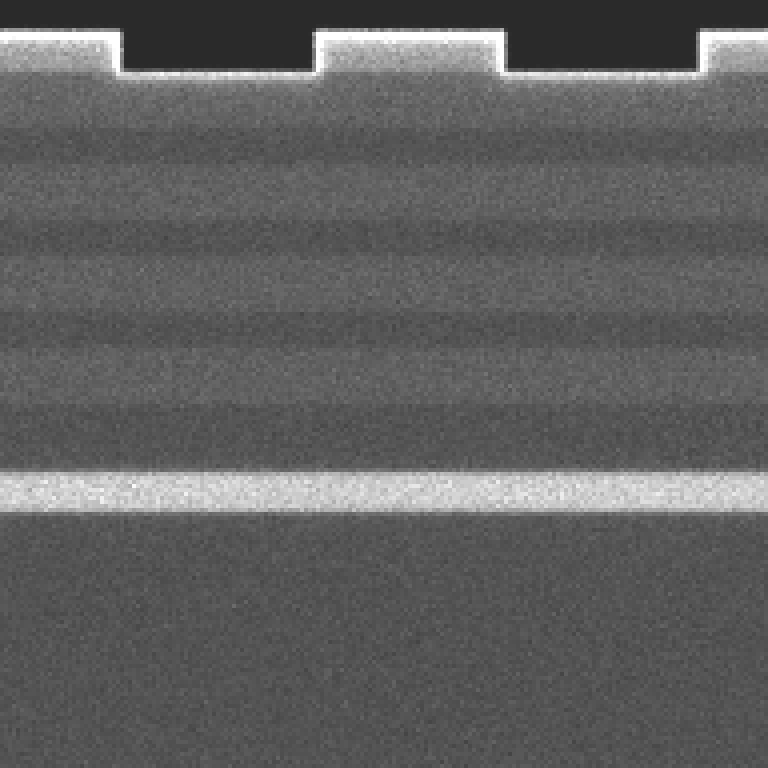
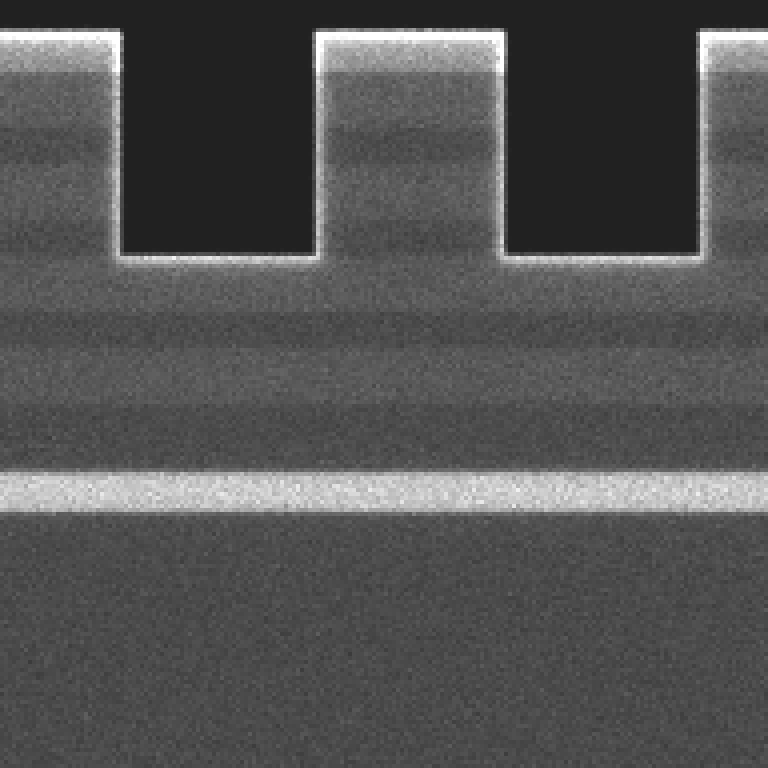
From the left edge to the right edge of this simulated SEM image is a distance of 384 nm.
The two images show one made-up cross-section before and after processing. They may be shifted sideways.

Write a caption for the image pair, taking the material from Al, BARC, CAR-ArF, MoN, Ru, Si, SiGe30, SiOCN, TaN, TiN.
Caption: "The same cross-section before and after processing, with Si and SiGe30 removed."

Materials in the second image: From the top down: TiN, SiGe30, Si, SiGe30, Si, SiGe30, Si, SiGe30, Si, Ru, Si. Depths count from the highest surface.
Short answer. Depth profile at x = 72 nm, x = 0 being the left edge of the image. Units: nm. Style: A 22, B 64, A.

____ empty 112, SiGe30 28, Si 18, SiGe30 28, Si 34, Ru 20, Si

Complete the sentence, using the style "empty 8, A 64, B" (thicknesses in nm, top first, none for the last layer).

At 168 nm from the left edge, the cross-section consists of TiN 20, SiGe30 28, Si 18, SiGe30 28, Si 18, SiGe30 28, Si 18, SiGe30 28, Si 34, Ru 20, Si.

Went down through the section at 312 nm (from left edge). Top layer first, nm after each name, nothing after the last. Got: empty 112, SiGe30 28, Si 18, SiGe30 28, Si 34, Ru 20, Si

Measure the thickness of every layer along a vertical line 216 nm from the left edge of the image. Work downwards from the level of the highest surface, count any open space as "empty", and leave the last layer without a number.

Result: TiN 20, SiGe30 28, Si 18, SiGe30 28, Si 18, SiGe30 28, Si 18, SiGe30 28, Si 34, Ru 20, Si